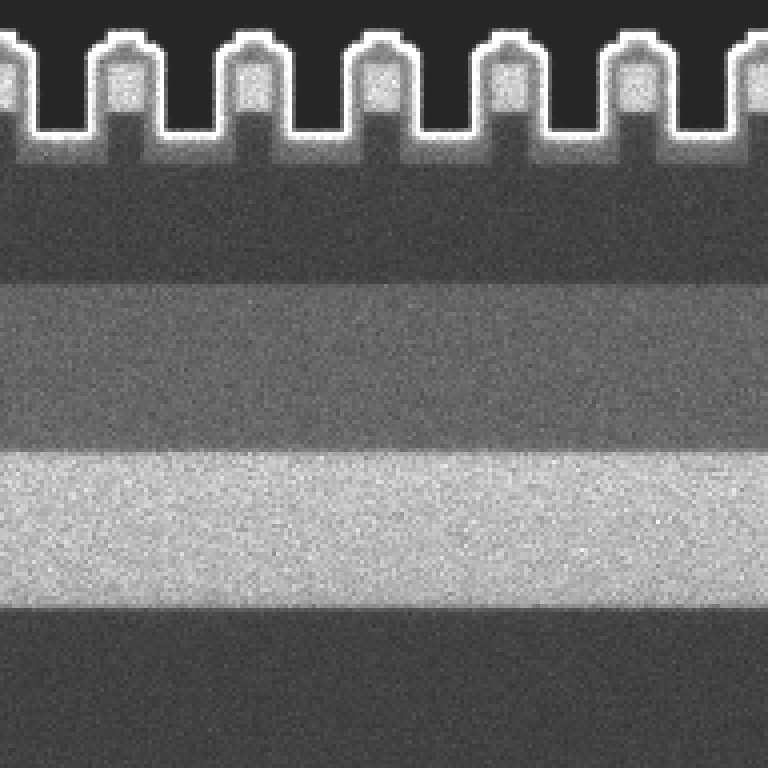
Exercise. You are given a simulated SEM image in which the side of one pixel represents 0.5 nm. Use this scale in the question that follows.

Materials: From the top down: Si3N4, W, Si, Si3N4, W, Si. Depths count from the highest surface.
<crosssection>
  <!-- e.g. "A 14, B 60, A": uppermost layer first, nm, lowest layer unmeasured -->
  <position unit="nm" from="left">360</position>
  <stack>empty 50, Si3N4 16, Si 60, Si3N4 84, W 78, Si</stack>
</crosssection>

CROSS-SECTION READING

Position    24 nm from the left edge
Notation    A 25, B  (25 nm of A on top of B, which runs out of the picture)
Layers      empty 50, Si3N4 16, Si 60, Si3N4 84, W 78, Si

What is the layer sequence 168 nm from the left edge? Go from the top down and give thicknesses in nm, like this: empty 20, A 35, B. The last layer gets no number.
empty 50, Si3N4 16, Si 60, Si3N4 84, W 78, Si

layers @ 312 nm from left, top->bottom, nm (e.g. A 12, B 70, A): Si3N4 16, W 24, Si 86, Si3N4 84, W 78, Si